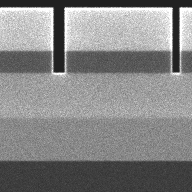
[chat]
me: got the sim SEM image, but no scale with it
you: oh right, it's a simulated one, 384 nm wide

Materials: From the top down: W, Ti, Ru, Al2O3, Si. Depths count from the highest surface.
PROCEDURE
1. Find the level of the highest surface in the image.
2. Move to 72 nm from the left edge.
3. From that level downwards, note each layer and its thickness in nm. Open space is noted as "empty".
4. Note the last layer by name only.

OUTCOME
W 86, Ti 44, Ru 90, Al2O3 86, Si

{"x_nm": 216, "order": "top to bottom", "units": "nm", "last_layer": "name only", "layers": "W 86, Ti 44, Ru 90, Al2O3 86, Si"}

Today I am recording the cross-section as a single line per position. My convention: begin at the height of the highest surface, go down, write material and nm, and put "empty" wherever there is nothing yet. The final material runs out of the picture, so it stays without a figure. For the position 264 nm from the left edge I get W 86, Ti 44, Ru 90, Al2O3 86, Si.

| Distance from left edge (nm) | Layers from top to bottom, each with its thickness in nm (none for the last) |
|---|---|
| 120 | empty 130, Ru 90, Al2O3 86, Si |